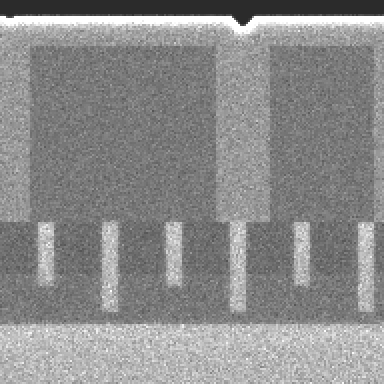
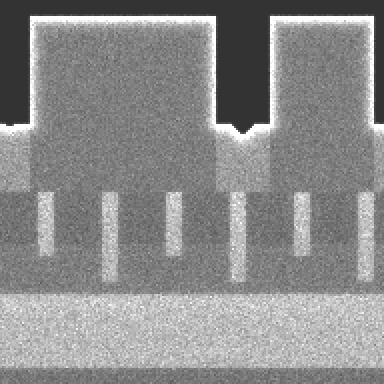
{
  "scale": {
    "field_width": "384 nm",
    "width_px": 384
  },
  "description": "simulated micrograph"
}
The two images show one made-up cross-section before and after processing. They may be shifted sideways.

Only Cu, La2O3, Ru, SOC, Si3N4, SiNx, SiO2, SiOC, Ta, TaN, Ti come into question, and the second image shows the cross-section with SiO2 removed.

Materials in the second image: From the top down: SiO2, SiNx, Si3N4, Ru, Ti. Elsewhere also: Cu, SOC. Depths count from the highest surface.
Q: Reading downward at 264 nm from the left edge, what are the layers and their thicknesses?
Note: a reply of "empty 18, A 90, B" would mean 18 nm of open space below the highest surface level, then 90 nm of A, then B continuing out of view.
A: empty 108, SiO2 68, SiNx 52, Si3N4 50, Ru 74, Ti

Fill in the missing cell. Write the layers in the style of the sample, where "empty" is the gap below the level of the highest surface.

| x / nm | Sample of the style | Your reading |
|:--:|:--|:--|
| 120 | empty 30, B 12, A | SOC 176, SiNx 52, Si3N4 50, Ru 74, Ti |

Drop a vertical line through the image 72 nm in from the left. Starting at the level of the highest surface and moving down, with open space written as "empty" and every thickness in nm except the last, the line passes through SOC 176, SiNx 52, Si3N4 50, Ru 74, Ti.